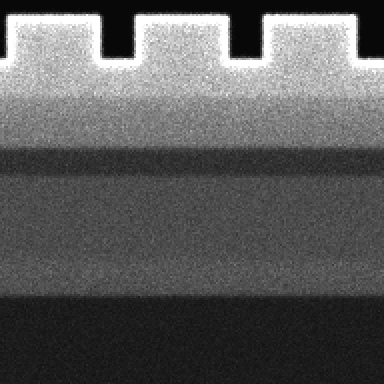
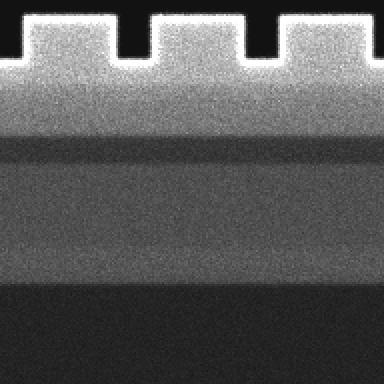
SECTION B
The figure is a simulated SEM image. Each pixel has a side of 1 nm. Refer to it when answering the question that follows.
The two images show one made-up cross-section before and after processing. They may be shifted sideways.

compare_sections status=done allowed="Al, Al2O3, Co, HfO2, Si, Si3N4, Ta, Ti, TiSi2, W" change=removed material="HfO2"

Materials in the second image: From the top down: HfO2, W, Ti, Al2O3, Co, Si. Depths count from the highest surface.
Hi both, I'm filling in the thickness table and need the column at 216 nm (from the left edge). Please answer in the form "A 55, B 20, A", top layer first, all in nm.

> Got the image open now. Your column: HfO2 68, W 52, Ti 28, Al2O3 84, Co 36, Si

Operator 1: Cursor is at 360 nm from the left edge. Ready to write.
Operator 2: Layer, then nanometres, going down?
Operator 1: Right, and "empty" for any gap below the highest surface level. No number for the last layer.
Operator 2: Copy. HfO2 68, W 52, Ti 28, Al2O3 84, Co 36, Si